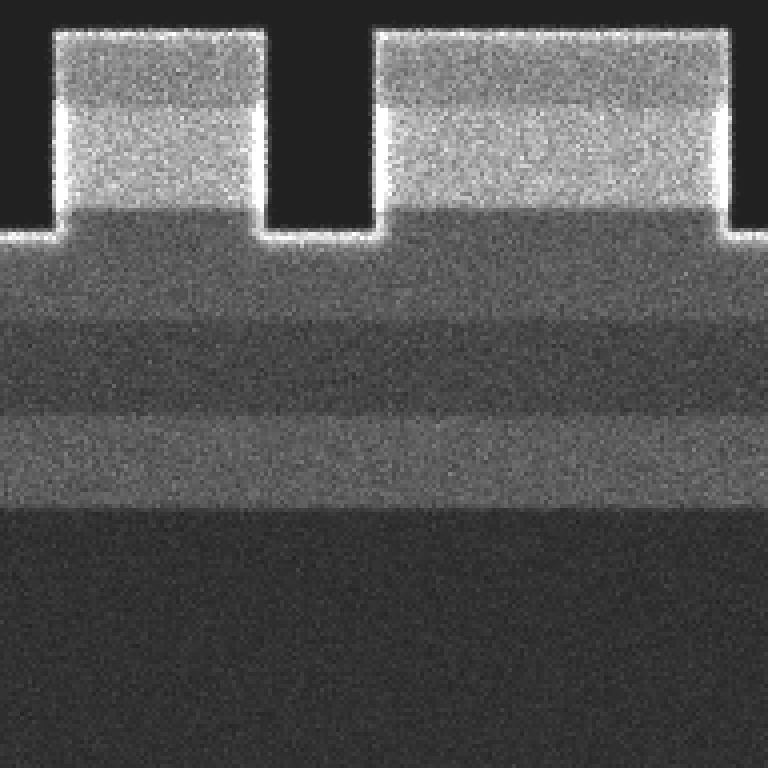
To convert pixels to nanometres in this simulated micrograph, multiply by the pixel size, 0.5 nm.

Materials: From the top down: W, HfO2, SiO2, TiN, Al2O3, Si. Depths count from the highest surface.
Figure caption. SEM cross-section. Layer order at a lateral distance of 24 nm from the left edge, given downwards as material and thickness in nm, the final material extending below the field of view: empty 100, SiO2 44, TiN 48, Al2O3 46, Si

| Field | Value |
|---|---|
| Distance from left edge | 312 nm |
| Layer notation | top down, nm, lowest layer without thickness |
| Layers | W 38, HfO2 50, SiO2 56, TiN 48, Al2O3 46, Si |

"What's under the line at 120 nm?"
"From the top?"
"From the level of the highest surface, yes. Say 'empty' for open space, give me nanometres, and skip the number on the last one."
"W 38, HfO2 50, SiO2 56, TiN 48, Al2O3 46, Si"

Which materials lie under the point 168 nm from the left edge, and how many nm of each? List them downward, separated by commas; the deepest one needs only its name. empty 100, SiO2 44, TiN 48, Al2O3 46, Si